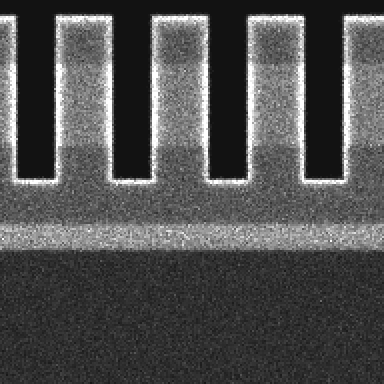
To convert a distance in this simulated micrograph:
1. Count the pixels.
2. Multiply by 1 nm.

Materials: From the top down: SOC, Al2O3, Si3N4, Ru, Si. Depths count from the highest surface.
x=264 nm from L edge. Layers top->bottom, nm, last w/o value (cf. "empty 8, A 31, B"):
SOC 48, Al2O3 82, Si3N4 78, Ru 26, Si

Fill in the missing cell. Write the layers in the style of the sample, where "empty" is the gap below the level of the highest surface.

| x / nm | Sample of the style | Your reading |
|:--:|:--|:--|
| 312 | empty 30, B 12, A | empty 164, Si3N4 44, Ru 26, Si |